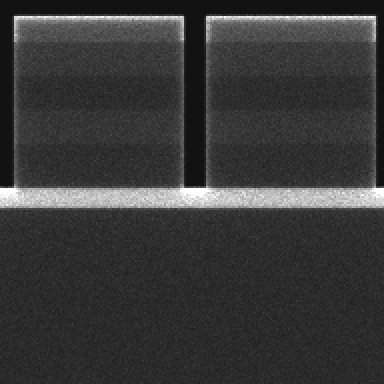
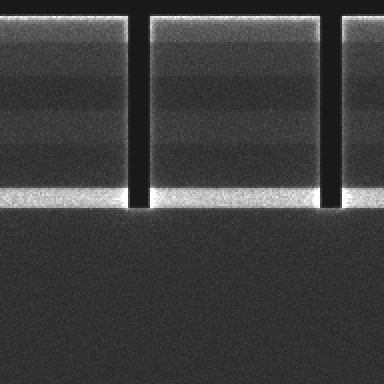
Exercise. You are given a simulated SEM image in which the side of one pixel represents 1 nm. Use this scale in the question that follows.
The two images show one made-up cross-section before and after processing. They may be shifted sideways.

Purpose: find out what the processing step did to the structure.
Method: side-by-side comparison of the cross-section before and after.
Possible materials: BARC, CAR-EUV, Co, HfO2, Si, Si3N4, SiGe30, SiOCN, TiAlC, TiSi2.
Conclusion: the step removed HfO2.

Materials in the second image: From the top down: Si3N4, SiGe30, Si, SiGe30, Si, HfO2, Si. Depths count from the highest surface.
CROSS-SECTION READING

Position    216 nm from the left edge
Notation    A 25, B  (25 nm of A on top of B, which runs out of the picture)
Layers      Si3N4 26, SiGe30 34, Si 34, SiGe30 34, Si 44, HfO2 20, Si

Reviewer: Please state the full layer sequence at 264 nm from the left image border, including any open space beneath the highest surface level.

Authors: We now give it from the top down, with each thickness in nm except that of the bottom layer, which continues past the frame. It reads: Si3N4 26, SiGe30 34, Si 34, SiGe30 34, Si 44, HfO2 20, Si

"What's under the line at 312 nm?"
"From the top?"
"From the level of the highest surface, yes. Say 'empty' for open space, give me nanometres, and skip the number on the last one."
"Si3N4 26, SiGe30 34, Si 34, SiGe30 34, Si 44, HfO2 20, Si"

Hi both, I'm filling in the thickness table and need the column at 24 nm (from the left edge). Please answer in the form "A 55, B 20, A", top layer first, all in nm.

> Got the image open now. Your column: Si3N4 26, SiGe30 34, Si 34, SiGe30 34, Si 44, HfO2 20, Si